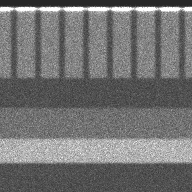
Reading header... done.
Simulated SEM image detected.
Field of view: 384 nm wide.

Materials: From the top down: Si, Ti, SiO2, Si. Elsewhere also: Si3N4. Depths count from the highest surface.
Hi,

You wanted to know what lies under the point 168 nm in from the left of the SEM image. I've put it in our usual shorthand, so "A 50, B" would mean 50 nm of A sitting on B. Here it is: Si 200, Ti 62, SiO2 48, Si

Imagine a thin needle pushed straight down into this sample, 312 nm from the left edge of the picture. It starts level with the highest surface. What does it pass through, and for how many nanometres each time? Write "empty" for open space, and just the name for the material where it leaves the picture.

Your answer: Si 200, Ti 62, SiO2 48, Si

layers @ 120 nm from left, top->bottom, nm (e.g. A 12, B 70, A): Si 200, Ti 62, SiO2 48, Si